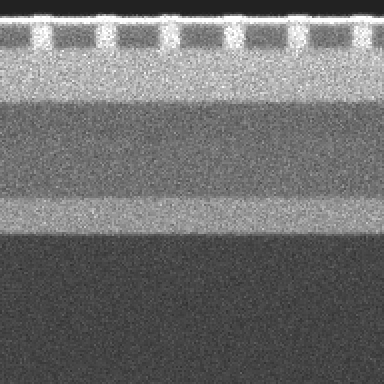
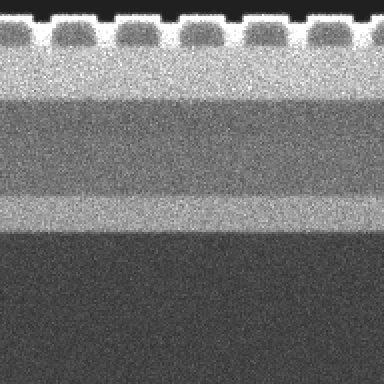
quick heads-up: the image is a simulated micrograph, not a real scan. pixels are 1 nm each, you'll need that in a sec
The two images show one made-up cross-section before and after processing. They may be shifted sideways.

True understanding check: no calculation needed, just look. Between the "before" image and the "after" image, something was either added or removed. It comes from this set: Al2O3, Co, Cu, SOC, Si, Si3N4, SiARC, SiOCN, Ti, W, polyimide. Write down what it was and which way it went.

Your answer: SOC (removed)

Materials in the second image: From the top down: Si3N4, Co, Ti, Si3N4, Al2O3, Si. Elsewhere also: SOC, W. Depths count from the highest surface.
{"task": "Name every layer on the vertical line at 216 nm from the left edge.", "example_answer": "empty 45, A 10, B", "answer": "Si3N4 30, Co 54, Ti 36, Si3N4 60, Al2O3 36, Si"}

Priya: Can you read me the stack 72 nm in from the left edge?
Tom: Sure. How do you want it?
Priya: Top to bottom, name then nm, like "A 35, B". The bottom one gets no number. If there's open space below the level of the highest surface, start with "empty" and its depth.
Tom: Si3N4 30, Co 54, Ti 36, Si3N4 60, Al2O3 36, Si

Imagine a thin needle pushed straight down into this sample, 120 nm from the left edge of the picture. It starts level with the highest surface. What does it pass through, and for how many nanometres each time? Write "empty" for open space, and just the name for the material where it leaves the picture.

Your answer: Si3N4 30, Co 54, Ti 36, Si3N4 60, Al2O3 36, Si